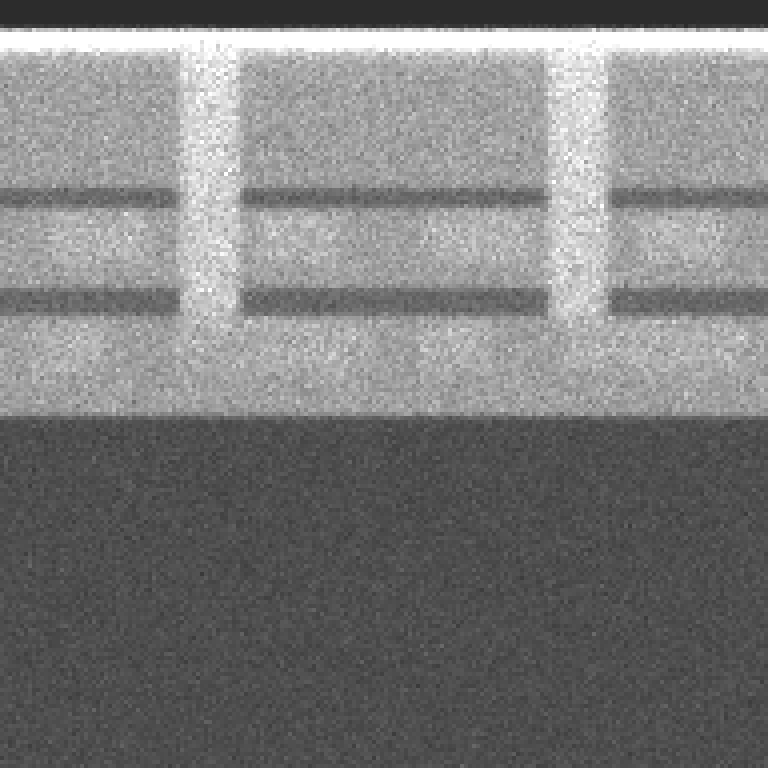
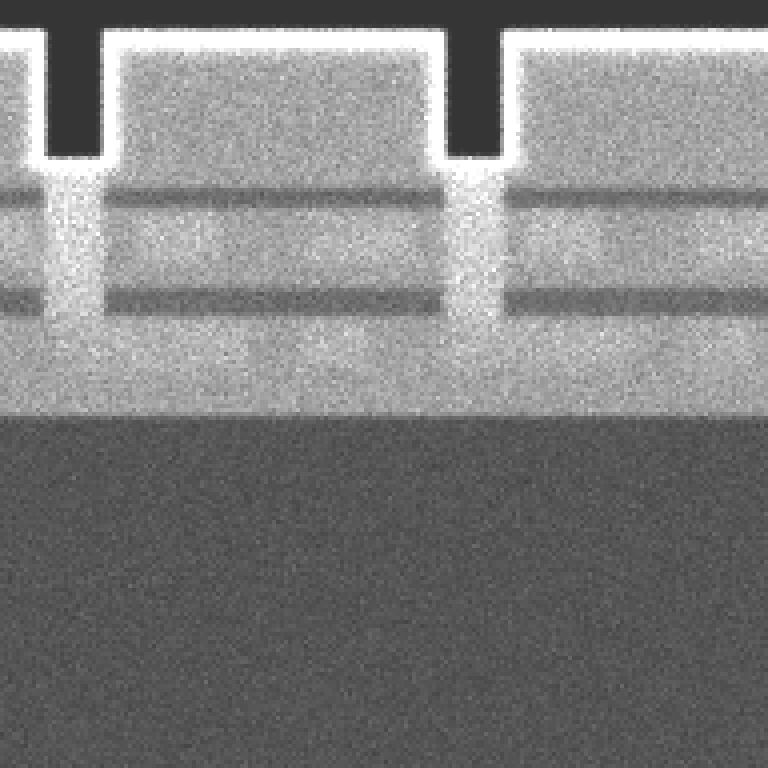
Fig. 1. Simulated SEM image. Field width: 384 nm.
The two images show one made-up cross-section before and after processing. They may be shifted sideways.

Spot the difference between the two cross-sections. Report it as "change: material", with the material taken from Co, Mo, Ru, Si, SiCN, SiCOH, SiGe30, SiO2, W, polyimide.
removed: Ru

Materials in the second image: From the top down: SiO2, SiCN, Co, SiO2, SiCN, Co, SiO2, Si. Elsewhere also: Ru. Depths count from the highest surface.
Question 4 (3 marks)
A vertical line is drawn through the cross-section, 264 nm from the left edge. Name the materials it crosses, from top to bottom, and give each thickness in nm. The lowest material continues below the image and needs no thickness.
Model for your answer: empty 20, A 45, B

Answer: SiO2 78, SiCN 10, Co 28, SiO2 12, SiCN 14, Co 28, SiO2 22, Si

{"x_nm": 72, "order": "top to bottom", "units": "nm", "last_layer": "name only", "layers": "SiO2 78, SiCN 10, Co 28, SiO2 12, SiCN 14, Co 28, SiO2 22, Si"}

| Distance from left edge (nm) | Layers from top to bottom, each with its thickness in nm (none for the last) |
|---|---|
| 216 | SiO2 78, SiCN 10, SiO2 40, SiCN 14, SiO2 50, Si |